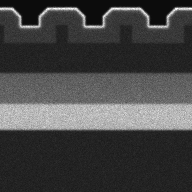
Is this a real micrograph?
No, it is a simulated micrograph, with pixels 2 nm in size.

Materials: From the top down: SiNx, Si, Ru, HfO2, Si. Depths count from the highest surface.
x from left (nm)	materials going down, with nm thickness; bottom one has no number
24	SiNx 70, Si 60, Ru 62, HfO2 52, Si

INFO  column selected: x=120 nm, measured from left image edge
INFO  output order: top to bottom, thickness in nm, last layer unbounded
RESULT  SiNx 34, Si 96, Ru 62, HfO2 52, Si